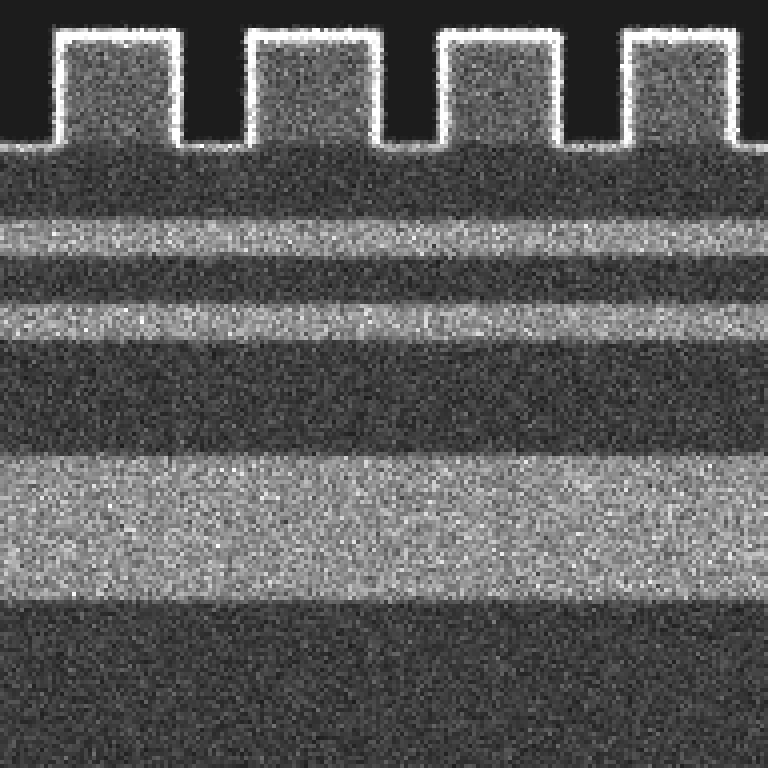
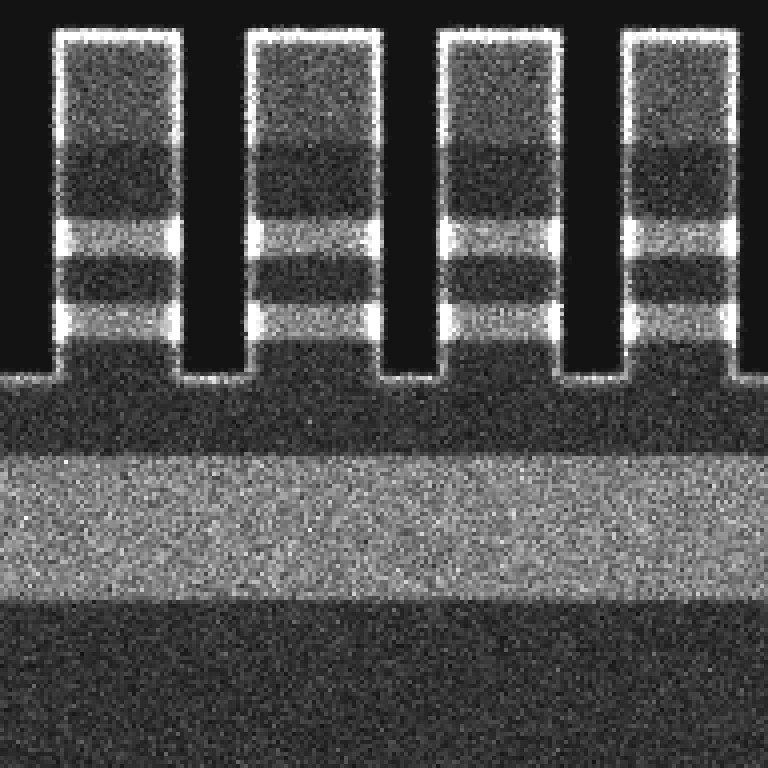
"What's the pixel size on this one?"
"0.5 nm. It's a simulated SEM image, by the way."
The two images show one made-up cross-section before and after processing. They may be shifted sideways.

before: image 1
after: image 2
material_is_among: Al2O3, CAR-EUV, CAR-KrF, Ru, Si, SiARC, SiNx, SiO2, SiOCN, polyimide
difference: Al2O3 and Si, removed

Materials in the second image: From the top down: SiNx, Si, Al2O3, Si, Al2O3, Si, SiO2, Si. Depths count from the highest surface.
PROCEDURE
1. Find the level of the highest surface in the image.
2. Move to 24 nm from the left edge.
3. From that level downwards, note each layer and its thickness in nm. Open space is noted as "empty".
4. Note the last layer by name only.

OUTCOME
empty 172, Si 40, SiO2 72, Si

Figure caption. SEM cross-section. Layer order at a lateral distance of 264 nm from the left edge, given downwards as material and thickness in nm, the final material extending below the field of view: SiNx 56, Si 38, Al2O3 18, Si 24, Al2O3 18, Si 58, SiO2 72, Si